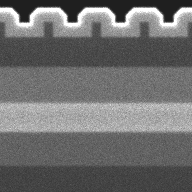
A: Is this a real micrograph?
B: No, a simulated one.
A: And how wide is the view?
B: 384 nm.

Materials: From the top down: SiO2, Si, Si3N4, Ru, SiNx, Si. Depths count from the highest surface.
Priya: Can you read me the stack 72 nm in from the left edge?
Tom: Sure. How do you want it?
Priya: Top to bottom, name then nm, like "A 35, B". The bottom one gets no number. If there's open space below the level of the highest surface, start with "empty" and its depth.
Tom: empty 2, SiO2 56, Si 60, Si3N4 72, Ru 58, SiNx 68, Si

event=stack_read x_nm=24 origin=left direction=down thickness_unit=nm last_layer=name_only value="empty 2, SiO2 56, Si 60, Si3N4 72, Ru 58, SiNx 68, Si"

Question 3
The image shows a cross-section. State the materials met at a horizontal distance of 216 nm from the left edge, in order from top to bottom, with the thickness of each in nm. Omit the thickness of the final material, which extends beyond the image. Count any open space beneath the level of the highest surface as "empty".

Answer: empty 2, SiO2 56, Si 60, Si3N4 72, Ru 58, SiNx 68, Si